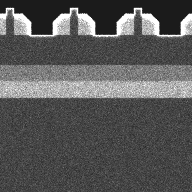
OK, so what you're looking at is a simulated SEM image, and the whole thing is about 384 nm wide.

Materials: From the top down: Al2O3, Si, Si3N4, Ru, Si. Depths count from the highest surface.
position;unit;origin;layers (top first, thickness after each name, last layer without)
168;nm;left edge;empty 12, Al2O3 42, Si 60, Si3N4 32, Ru 34, Si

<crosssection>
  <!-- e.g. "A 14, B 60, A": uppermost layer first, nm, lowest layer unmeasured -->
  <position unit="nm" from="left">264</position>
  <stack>empty 12, Al2O3 42, Si 60, Si3N4 32, Ru 34, Si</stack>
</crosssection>